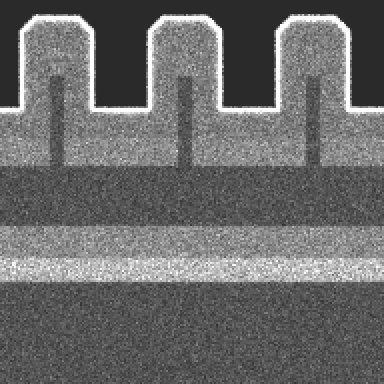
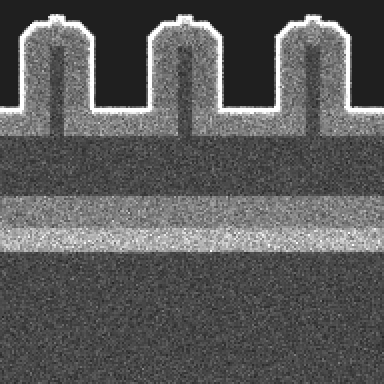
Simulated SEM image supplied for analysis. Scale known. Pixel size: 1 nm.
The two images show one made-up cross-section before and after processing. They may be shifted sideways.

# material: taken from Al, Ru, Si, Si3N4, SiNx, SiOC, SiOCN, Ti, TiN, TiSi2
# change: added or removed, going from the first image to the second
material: SiNx
change: removed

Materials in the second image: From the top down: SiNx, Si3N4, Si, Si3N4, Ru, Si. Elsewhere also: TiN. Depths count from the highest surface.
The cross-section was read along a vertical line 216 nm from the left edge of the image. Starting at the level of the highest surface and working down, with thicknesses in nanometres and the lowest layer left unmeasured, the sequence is empty 16, SiNx 76, Si3N4 28, Si 60, Si3N4 32, Ru 24, Si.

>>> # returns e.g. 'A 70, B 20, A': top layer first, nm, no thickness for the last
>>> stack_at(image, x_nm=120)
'empty 92, Si3N4 28, Si 60, Si3N4 32, Ru 24, Si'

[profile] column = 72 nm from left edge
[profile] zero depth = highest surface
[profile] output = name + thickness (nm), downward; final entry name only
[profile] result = empty 6, SiNx 86, Si3N4 28, Si 60, Si3N4 32, Ru 24, Si